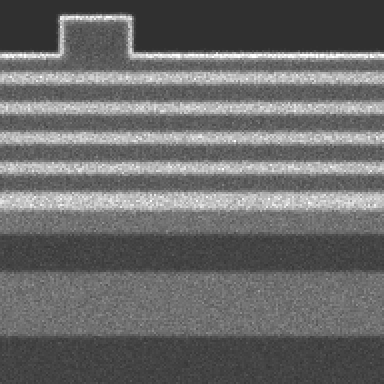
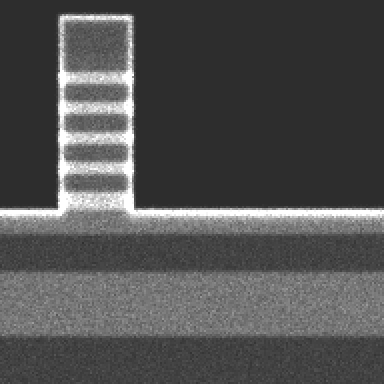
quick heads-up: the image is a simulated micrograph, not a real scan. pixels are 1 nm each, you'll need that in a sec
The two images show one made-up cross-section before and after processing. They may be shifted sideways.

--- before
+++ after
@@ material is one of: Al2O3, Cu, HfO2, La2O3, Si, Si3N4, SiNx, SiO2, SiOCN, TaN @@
HfO2 and Si3N4 removed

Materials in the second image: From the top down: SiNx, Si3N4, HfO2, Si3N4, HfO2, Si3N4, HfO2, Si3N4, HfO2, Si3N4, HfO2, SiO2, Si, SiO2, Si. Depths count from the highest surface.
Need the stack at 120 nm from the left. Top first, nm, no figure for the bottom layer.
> SiNx 38, Si3N4 18, HfO2 12, Si3N4 18, HfO2 12, Si3N4 18, HfO2 12, Si3N4 18, HfO2 12, Si3N4 18, HfO2 18, SiO2 24, Si 38, SiO2 64, Si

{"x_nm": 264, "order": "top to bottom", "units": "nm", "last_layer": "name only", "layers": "empty 194, SiO2 24, Si 38, SiO2 64, Si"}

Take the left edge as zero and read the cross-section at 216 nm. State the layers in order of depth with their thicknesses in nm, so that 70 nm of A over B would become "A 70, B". empty 194, SiO2 24, Si 38, SiO2 64, Si